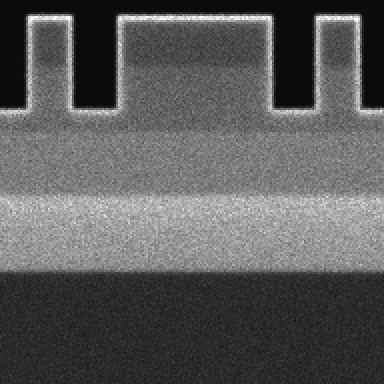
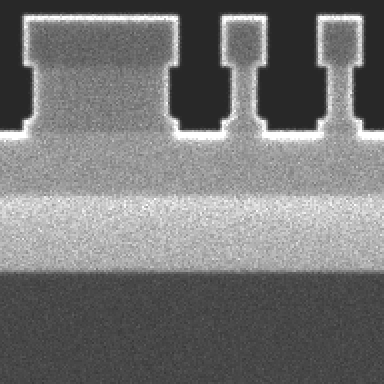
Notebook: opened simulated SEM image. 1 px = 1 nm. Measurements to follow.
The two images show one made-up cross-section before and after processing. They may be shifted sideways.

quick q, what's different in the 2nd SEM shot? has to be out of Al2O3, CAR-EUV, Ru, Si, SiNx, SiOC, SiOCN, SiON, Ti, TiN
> TiN removed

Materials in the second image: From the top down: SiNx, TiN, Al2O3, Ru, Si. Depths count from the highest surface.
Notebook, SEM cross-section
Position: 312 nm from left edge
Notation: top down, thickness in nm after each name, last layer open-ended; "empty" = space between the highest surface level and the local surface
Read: empty 116, Al2O3 64, Ru 76, Si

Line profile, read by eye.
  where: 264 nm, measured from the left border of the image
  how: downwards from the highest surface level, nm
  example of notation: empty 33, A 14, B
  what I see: SiNx 50, empty 54, TiN 12, Al2O3 64, Ru 76, Si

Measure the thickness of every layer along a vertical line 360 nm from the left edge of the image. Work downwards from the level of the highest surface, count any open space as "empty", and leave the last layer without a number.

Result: SiNx 50, empty 54, TiN 12, Al2O3 64, Ru 76, Si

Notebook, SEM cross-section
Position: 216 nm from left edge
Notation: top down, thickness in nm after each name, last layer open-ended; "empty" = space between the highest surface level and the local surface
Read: empty 116, Al2O3 64, Ru 76, Si